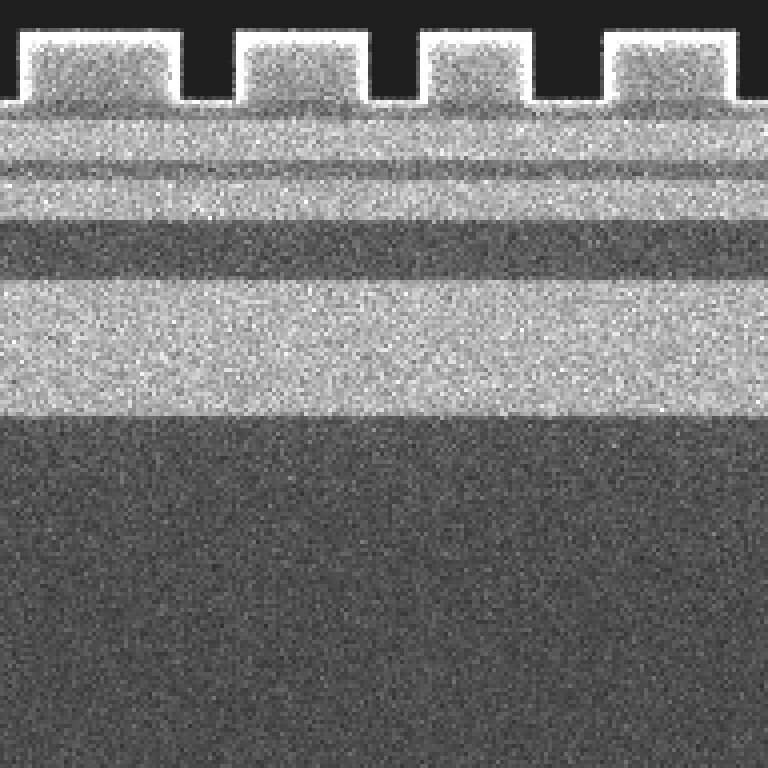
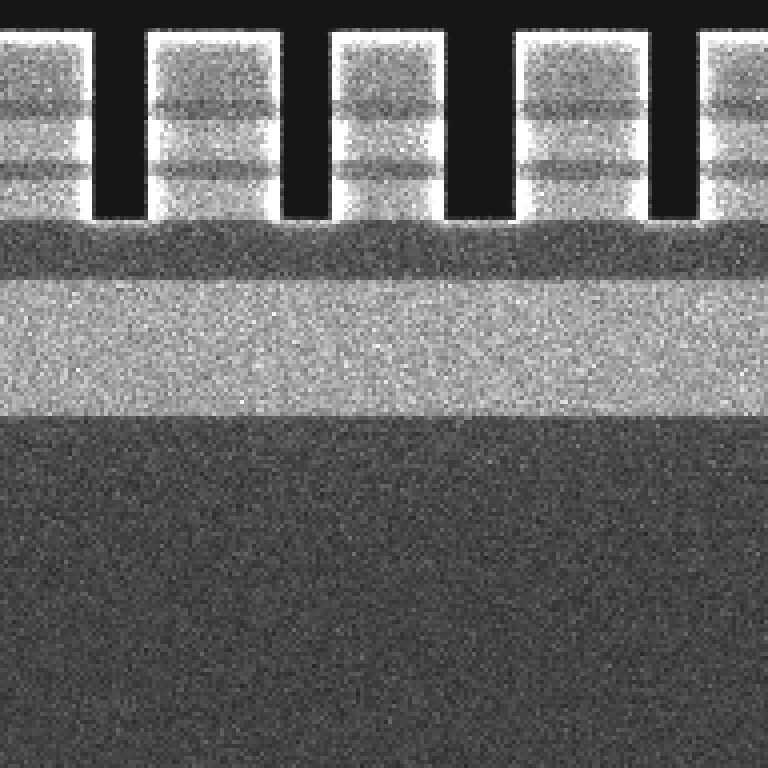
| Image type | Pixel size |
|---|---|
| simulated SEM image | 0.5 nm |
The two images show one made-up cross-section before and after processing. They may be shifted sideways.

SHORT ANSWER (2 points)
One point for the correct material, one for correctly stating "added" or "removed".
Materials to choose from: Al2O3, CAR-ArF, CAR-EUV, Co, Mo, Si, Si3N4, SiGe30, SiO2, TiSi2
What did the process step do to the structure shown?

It removed SiGe30 and SiO2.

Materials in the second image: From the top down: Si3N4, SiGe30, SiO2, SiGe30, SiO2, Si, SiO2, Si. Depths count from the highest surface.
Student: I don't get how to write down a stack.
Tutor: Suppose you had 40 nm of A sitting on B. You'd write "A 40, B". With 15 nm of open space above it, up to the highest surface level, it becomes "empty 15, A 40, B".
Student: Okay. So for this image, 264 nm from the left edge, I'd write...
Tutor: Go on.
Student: Si3N4 34, SiGe30 10, SiO2 20, SiGe30 10, SiO2 20, Si 30, SiO2 68, Si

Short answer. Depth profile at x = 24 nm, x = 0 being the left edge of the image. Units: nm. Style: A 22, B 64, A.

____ Si3N4 34, SiGe30 10, SiO2 20, SiGe30 10, SiO2 20, Si 30, SiO2 68, Si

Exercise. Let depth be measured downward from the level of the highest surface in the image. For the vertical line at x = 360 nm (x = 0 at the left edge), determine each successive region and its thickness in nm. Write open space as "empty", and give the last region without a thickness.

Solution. Si3N4 34, SiGe30 10, SiO2 20, SiGe30 10, SiO2 20, Si 30, SiO2 68, Si